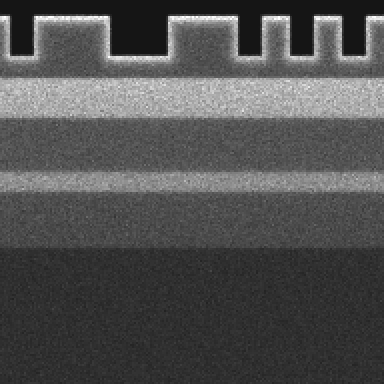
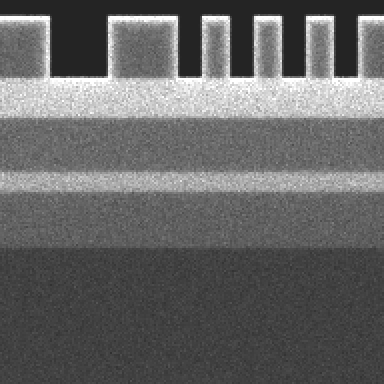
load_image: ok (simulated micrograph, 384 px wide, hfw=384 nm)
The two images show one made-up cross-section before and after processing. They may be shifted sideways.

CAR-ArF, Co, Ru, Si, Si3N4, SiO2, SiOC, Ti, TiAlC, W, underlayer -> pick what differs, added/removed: underlayer removed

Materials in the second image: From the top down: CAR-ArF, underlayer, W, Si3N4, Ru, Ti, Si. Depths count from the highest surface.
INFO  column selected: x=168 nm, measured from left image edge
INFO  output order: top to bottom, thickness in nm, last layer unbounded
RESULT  CAR-ArF 40, underlayer 22, W 40, Si3N4 54, Ru 20, Ti 56, Si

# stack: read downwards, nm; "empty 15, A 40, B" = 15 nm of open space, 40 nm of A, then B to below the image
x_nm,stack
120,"CAR-ArF 40, underlayer 22, W 40, Si3N4 54, Ru 20, Ti 56, Si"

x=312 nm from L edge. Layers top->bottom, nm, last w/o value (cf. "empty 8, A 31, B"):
CAR-ArF 40, underlayer 22, W 40, Si3N4 54, Ru 20, Ti 56, Si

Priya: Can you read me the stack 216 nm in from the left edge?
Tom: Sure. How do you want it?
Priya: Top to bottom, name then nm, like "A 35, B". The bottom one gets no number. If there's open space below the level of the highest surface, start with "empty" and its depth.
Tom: CAR-ArF 40, underlayer 22, W 40, Si3N4 54, Ru 20, Ti 56, Si